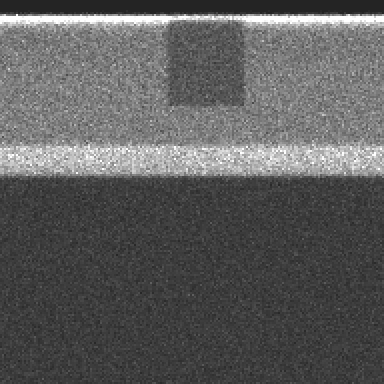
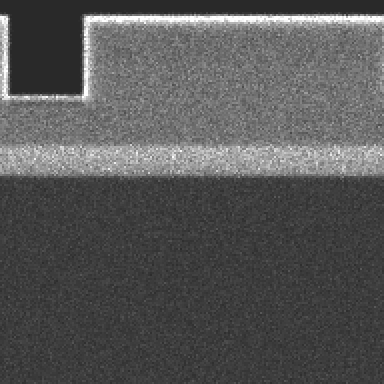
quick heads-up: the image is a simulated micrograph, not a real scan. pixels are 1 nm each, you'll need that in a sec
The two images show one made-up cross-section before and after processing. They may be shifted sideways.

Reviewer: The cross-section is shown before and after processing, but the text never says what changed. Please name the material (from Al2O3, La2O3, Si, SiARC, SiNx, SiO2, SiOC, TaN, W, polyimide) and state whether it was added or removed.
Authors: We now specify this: SiNx, removed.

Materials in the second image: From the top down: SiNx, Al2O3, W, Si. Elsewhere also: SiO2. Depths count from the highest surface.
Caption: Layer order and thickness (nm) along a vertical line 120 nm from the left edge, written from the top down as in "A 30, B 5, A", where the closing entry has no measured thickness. SiO2 46, Al2O3 84, W 30, Si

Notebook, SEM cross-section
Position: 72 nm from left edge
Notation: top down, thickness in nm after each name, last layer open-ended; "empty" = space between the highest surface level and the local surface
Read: empty 80, SiNx 10, Al2O3 40, W 30, Si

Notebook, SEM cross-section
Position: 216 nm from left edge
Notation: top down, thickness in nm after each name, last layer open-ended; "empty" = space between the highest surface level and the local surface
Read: SiO2 46, Al2O3 84, W 30, Si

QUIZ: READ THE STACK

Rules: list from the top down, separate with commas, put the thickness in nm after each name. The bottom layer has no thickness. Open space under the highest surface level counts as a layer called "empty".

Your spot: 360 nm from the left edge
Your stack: SiO2 46, Al2O3 84, W 30, Si